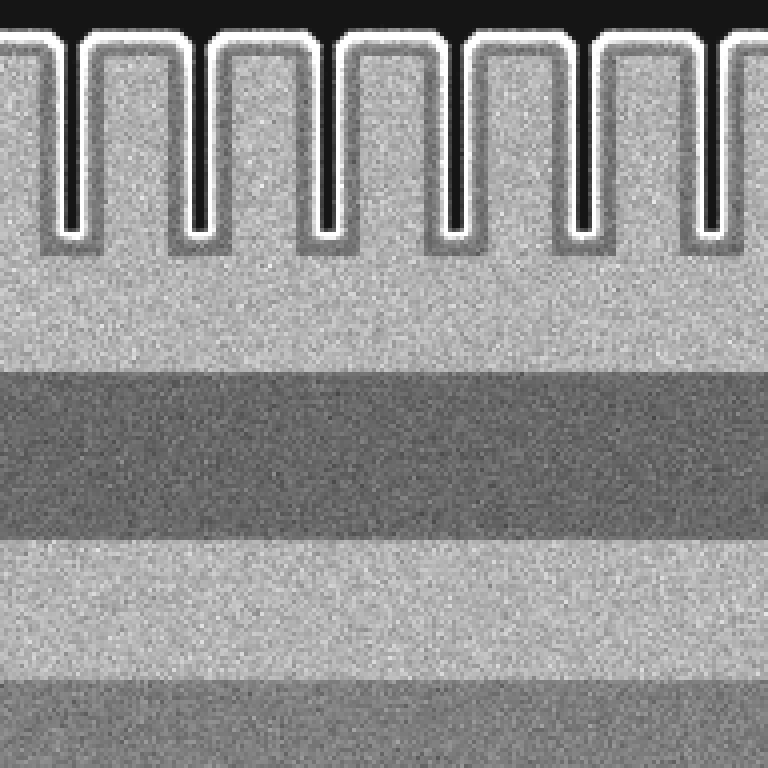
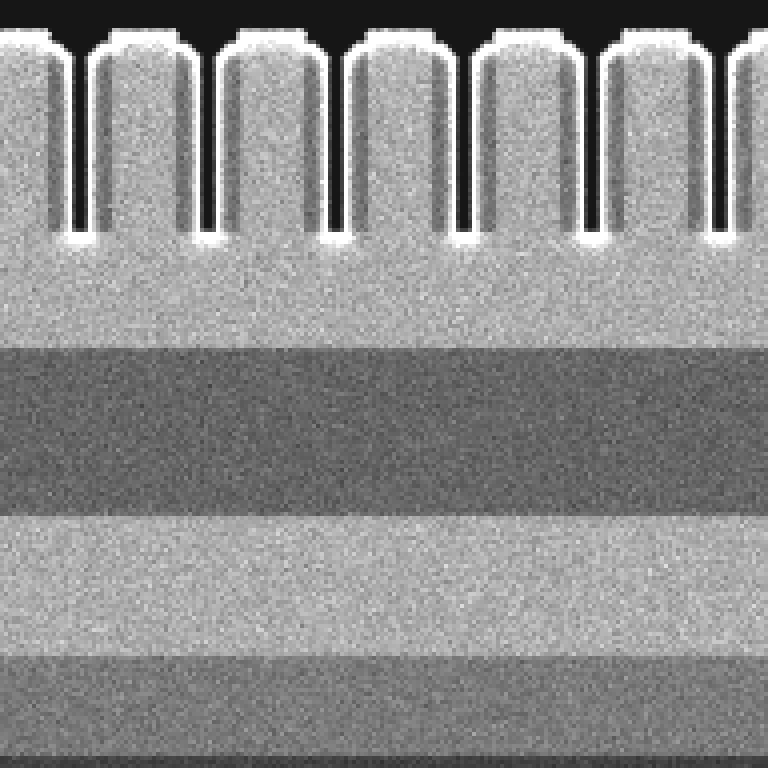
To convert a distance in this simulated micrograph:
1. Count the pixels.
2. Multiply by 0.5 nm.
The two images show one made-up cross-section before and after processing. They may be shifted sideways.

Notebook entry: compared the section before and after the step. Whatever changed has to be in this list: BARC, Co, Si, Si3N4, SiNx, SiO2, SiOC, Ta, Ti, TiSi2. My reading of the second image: SiNx removed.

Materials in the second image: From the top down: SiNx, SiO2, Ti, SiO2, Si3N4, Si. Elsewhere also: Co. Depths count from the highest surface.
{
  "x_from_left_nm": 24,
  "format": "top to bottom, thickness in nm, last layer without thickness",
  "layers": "empty 6, SiNx 94, SiO2 58, Ti 84, SiO2 70, Si3N4 50, Si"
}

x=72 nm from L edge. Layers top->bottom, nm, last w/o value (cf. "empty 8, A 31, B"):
Co 76, SiO2 82, Ti 84, SiO2 70, Si3N4 50, Si